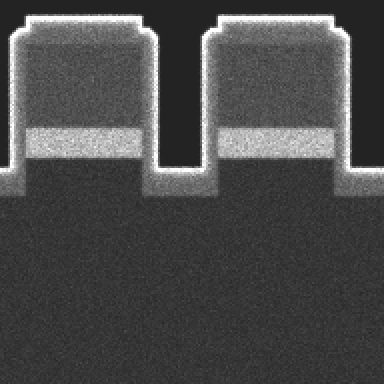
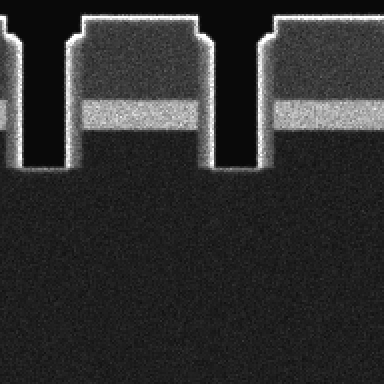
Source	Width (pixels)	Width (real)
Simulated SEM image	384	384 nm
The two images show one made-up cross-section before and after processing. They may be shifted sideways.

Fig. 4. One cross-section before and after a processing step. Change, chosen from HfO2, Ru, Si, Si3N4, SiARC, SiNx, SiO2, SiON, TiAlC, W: SiO2 removed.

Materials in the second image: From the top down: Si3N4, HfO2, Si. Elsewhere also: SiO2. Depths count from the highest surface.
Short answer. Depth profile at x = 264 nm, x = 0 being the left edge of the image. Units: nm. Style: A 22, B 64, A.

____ empty 20, SiO2 132, Si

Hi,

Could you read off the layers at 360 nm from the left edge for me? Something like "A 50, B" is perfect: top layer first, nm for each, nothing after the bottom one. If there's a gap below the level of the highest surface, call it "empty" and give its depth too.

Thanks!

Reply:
Si3N4 84, HfO2 30, Si